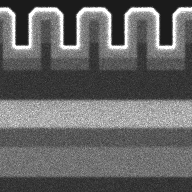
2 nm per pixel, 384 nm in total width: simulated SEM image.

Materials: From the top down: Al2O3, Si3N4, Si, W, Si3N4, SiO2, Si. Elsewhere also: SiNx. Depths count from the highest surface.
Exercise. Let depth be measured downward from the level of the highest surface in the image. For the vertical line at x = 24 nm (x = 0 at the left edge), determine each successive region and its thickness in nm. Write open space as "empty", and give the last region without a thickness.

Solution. empty 8, Al2O3 92, Si3N4 24, Si 60, W 56, Si3N4 38, SiO2 60, Si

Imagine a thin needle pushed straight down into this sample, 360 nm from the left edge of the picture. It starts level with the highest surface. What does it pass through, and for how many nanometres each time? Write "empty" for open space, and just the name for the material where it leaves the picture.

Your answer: Al2O3 100, Si3N4 24, Si 60, W 56, Si3N4 38, SiO2 60, Si